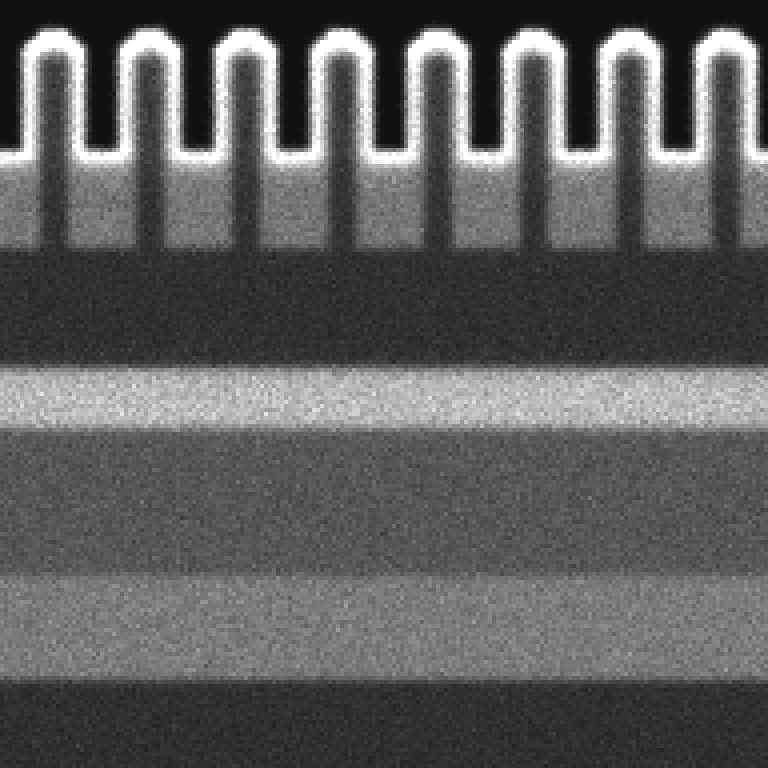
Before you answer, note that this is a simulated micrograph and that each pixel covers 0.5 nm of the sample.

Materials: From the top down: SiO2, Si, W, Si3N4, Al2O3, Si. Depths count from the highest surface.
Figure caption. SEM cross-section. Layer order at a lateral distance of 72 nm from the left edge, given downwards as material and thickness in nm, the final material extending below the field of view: SiO2 12, Si 156, W 30, Si3N4 74, Al2O3 52, Si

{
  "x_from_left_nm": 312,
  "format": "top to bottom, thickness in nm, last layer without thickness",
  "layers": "SiO2 12, Si 156, W 30, Si3N4 74, Al2O3 52, Si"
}